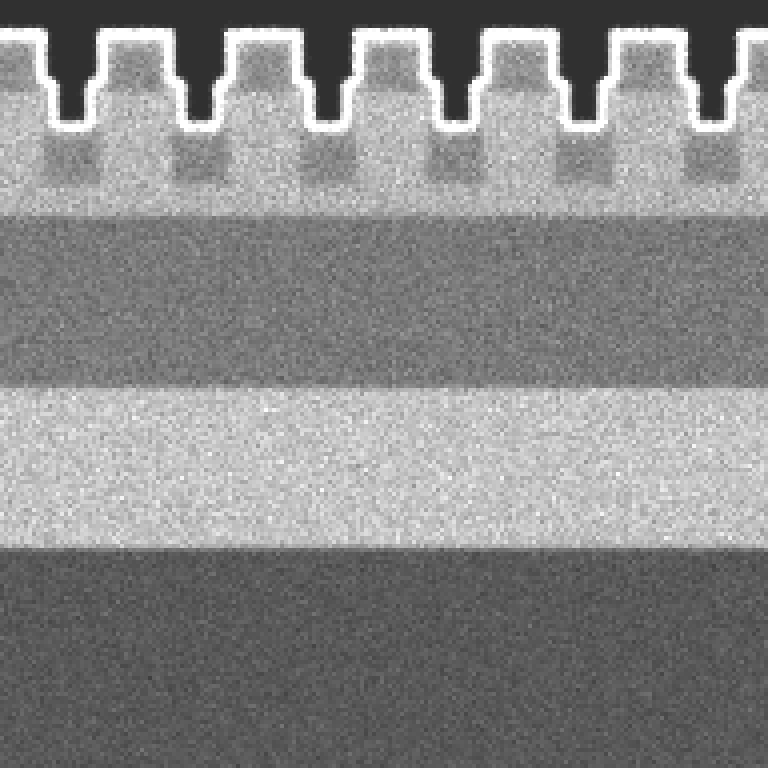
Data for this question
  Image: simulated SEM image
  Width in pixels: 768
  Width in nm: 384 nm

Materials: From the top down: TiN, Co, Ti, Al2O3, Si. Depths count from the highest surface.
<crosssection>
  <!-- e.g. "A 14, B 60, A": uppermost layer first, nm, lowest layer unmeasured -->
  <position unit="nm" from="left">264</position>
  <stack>TiN 30, Co 62, Ti 86, Al2O3 80, Si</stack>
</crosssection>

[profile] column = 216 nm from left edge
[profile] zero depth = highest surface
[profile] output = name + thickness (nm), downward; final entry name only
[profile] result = empty 24, TiN 52, Co 16, Ti 86, Al2O3 80, Si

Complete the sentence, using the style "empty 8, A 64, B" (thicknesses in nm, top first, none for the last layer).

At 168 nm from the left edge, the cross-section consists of empty 46, TiN 30, Co 16, Ti 86, Al2O3 80, Si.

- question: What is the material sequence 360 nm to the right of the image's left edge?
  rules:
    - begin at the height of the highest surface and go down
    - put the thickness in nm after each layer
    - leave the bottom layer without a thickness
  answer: empty 46, TiN 30, Co 16, Ti 86, Al2O3 80, Si